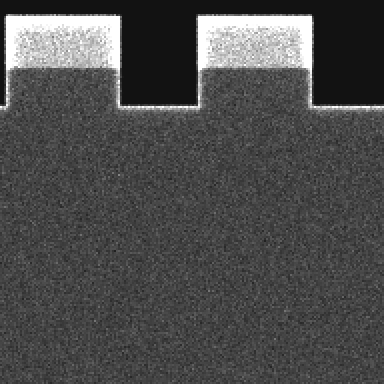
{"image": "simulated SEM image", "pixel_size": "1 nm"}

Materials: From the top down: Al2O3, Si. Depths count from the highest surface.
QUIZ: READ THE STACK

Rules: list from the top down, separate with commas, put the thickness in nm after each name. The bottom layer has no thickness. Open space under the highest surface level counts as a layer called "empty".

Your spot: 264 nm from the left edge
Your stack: Al2O3 52, Si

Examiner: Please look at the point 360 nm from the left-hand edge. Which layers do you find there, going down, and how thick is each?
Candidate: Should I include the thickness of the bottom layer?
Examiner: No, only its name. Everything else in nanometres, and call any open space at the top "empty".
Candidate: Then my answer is empty 90, Si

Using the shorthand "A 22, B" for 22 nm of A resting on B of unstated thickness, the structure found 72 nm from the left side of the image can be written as Al2O3 52, Si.